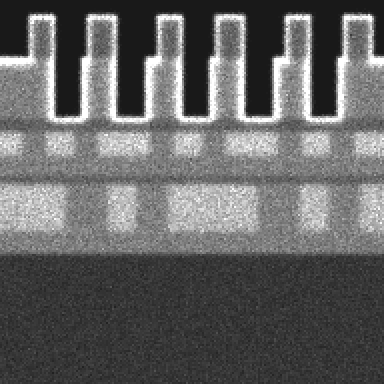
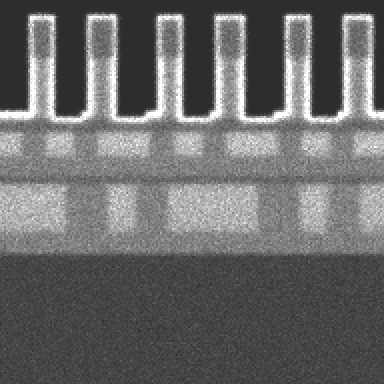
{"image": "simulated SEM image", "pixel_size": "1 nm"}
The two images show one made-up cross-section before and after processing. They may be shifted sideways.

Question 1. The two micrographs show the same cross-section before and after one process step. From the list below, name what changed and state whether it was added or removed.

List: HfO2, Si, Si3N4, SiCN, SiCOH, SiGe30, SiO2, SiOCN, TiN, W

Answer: SiO2, removed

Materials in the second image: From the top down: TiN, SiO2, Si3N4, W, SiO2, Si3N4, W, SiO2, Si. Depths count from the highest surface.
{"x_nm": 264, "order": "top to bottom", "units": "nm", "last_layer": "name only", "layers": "empty 102, Si3N4 14, W 24, SiO2 20, Si3N4 8, SiO2 70, Si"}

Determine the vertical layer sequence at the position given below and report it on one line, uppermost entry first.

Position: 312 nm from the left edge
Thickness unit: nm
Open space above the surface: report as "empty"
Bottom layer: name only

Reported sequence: empty 102, Si3N4 14, W 24, SiO2 20, Si3N4 8, W 48, SiO2 22, Si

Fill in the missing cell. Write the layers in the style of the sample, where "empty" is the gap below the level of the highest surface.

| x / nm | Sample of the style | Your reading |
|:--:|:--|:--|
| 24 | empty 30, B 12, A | empty 96, SiO2 6, Si3N4 14, SiO2 44, Si3N4 8, W 48, SiO2 22, Si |